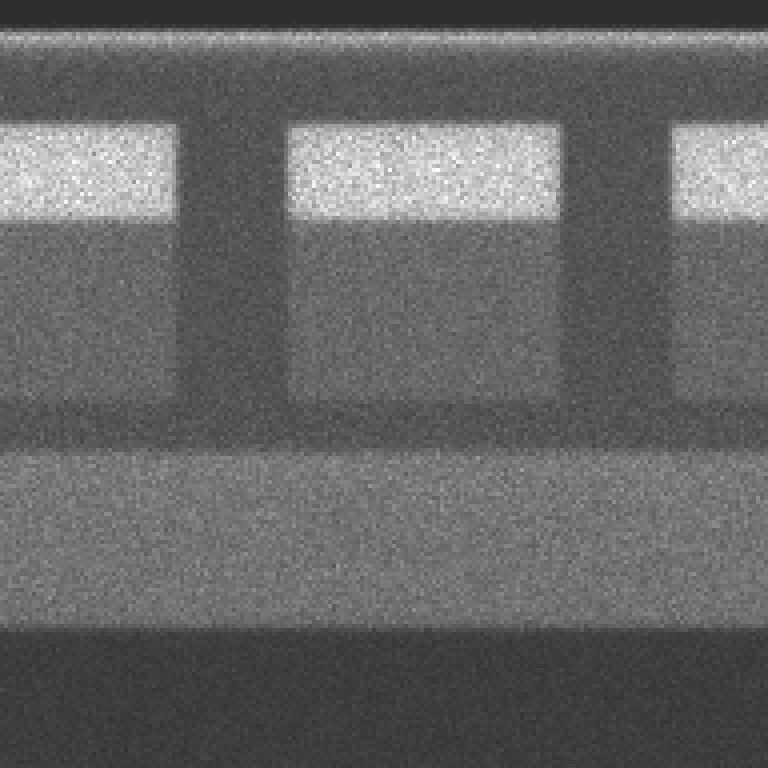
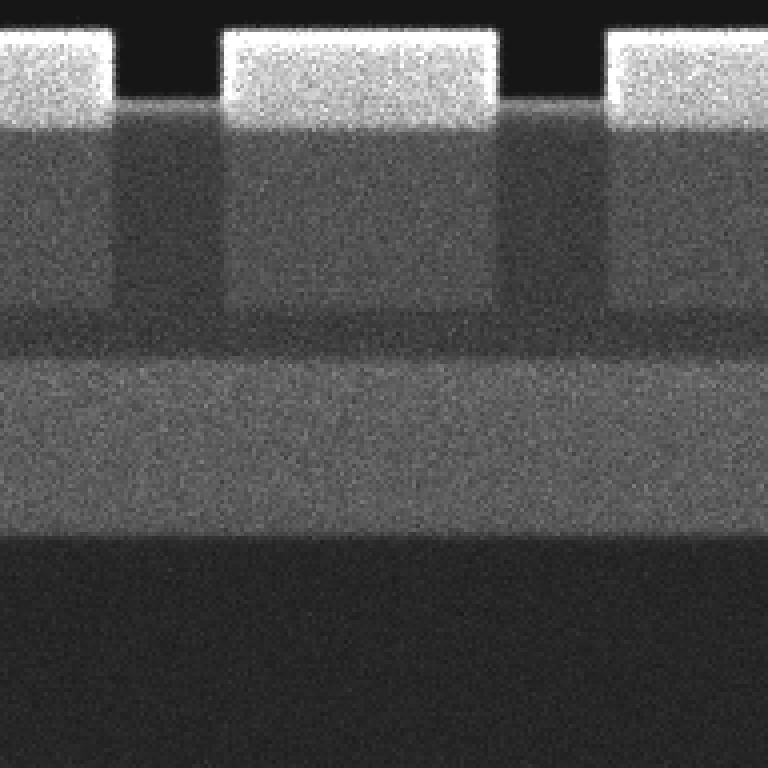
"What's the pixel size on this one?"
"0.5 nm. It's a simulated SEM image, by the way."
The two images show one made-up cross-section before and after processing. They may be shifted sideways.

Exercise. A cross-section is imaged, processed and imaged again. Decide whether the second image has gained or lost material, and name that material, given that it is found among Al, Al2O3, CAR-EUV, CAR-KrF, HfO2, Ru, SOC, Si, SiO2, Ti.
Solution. removed: SOC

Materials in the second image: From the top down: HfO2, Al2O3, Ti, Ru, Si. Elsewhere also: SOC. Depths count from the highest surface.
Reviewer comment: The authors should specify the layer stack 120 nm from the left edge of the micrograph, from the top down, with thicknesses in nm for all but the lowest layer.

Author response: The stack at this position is HfO2 48, Al2O3 90, Ti 26, Ru 88, Si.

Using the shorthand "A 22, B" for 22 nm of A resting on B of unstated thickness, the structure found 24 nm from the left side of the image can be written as HfO2 48, Al2O3 90, Ti 26, Ru 88, Si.